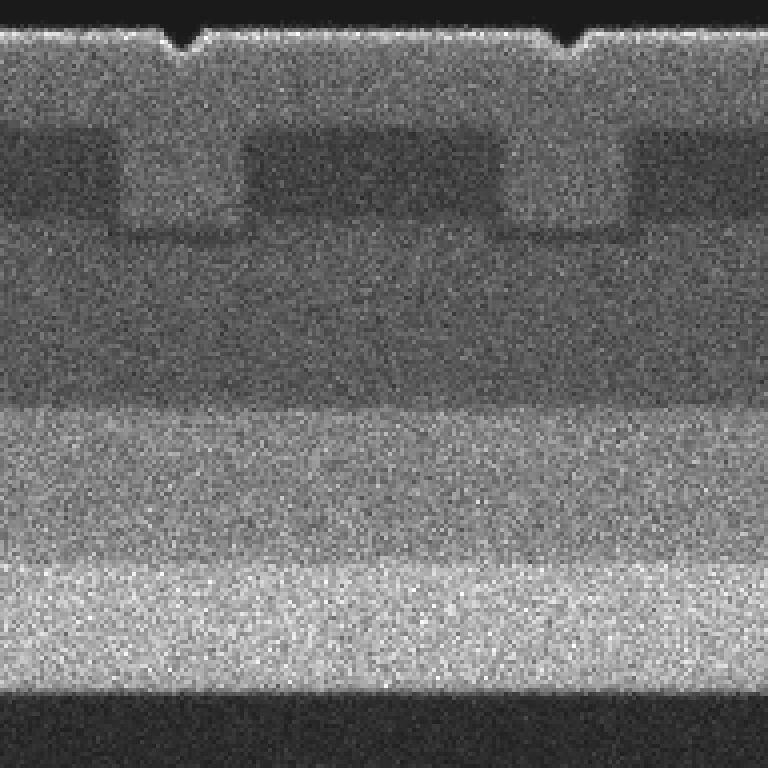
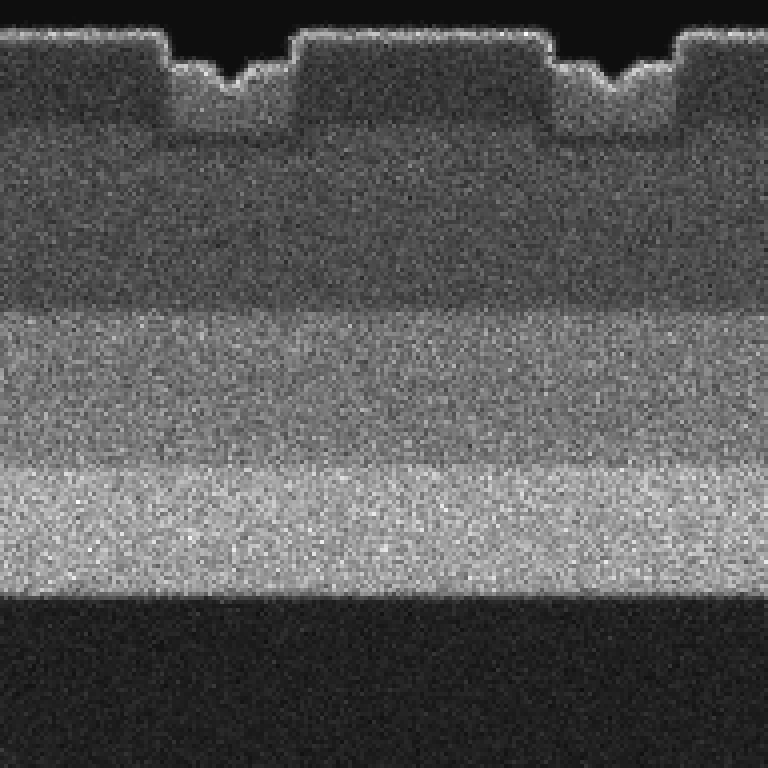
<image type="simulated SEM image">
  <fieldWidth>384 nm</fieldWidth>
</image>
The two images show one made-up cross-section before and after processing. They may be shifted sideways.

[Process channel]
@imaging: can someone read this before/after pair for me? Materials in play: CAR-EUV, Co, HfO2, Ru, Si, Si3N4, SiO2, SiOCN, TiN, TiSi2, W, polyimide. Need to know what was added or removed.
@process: Ru removed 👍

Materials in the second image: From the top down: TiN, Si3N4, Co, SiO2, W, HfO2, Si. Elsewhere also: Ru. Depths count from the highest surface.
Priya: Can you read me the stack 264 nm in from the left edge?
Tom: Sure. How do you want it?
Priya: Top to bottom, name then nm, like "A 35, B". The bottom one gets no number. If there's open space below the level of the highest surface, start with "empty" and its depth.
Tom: TiN 8, Si3N4 38, Co 36, SiO2 58, W 78, HfO2 64, Si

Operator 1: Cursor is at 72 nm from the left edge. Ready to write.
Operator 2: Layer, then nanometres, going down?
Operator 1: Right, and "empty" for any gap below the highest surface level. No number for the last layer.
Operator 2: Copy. TiN 8, Si3N4 38, Co 36, SiO2 58, W 78, HfO2 64, Si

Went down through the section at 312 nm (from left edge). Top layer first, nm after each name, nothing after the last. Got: empty 22, Ru 28, TiN 8, Co 24, SiO2 58, W 78, HfO2 64, Si